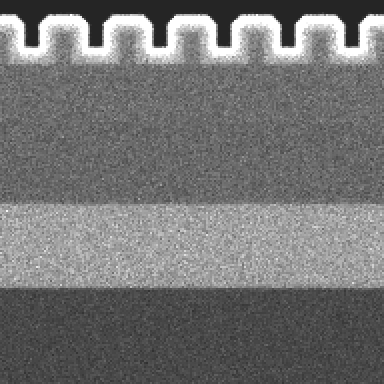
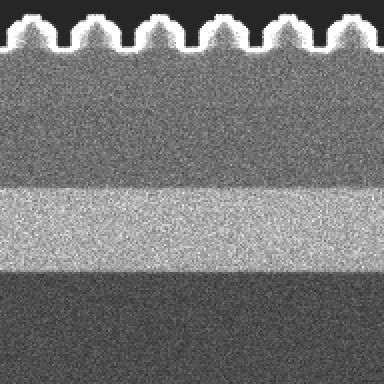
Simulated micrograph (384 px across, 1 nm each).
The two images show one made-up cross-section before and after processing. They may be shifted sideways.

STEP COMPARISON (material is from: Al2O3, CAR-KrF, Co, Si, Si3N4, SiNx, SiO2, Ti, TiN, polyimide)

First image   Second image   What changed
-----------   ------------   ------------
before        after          SiO2, removed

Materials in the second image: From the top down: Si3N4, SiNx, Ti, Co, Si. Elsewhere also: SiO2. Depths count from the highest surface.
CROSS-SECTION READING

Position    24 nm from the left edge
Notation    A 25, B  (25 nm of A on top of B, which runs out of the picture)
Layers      Si3N4 32, SiNx 58, Ti 82, Co 84, Si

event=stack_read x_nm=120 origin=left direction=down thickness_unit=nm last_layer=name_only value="empty 32, SiNx 58, Ti 82, Co 84, Si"